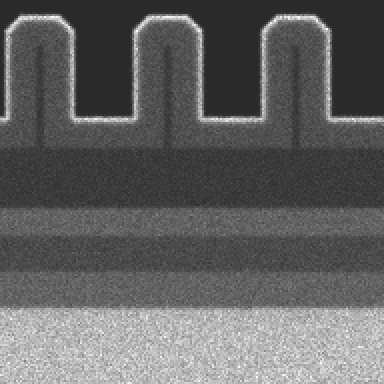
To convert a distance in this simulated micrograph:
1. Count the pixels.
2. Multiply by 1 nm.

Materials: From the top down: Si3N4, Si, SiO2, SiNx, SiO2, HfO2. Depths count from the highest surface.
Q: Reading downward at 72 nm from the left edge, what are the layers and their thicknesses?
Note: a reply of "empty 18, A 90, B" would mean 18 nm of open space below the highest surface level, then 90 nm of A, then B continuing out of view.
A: empty 14, Si3N4 118, Si 60, SiO2 28, SiNx 36, SiO2 36, HfO2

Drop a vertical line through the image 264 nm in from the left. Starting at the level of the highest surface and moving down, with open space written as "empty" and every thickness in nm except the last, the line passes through empty 12, Si3N4 120, Si 60, SiO2 28, SiNx 36, SiO2 36, HfO2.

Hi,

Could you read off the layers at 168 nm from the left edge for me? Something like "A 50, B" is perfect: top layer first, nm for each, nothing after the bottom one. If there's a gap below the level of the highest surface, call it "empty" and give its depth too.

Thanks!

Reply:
Si3N4 30, Si 162, SiO2 28, SiNx 36, SiO2 36, HfO2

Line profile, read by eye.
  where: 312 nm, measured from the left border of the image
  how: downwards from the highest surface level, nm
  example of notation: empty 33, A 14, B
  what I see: Si3N4 132, Si 60, SiO2 28, SiNx 36, SiO2 36, HfO2